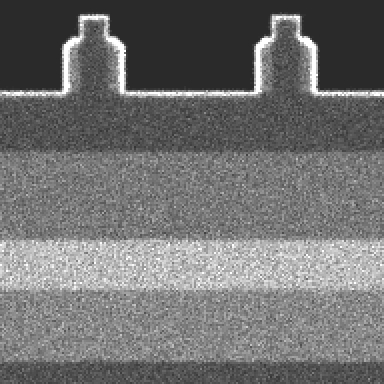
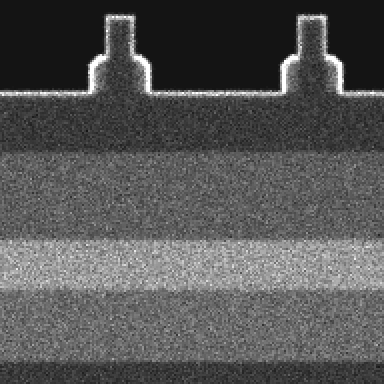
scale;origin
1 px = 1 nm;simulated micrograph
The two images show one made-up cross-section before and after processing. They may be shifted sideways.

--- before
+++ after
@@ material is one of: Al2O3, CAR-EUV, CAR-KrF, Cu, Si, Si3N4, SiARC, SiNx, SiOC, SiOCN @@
SiOCN removed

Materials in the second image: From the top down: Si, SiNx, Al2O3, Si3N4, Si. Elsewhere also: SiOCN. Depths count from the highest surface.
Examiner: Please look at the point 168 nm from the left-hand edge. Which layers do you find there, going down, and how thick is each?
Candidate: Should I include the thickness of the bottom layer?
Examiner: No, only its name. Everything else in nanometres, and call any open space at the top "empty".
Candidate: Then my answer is empty 76, Si 60, SiNx 88, Al2O3 50, Si3N4 72, Si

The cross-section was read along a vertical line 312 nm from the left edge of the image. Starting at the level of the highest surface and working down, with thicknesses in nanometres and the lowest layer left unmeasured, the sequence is Si 136, SiNx 88, Al2O3 50, Si3N4 72, Si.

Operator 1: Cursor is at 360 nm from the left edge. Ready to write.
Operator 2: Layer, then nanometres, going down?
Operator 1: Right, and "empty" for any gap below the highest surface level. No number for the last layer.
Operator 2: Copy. empty 76, Si 60, SiNx 88, Al2O3 50, Si3N4 72, Si